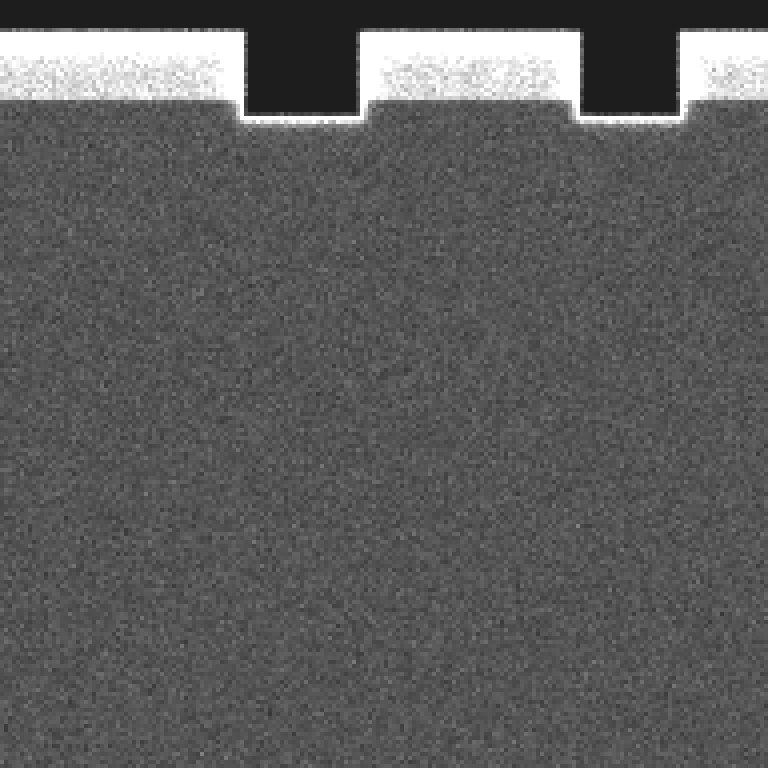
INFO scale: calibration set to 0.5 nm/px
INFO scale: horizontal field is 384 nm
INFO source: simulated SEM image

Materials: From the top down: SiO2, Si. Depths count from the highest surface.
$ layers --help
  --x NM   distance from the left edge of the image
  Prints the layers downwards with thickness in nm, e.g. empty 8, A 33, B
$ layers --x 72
SiO2 34, Si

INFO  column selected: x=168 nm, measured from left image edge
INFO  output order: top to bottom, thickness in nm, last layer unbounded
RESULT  empty 42, Si